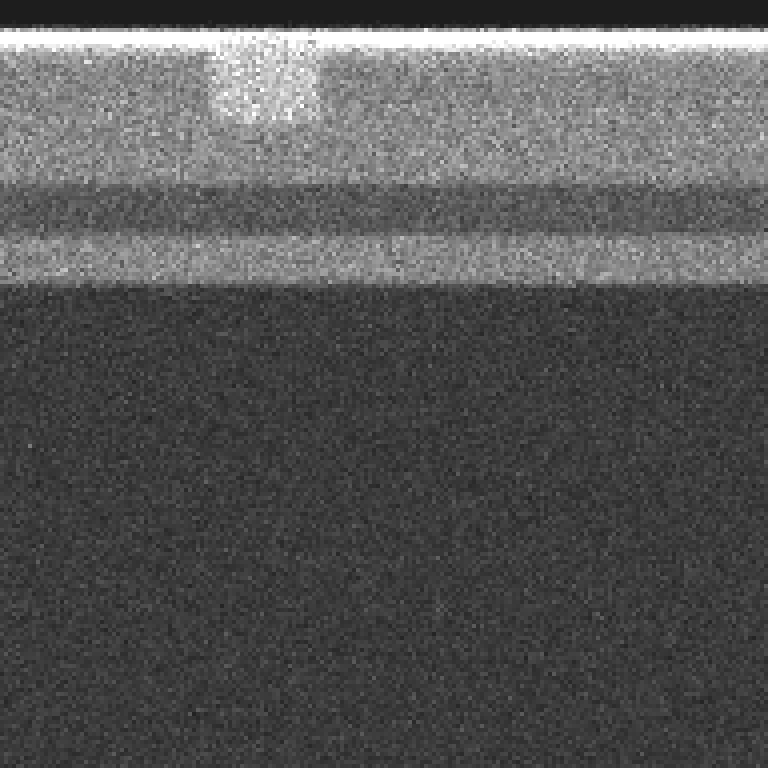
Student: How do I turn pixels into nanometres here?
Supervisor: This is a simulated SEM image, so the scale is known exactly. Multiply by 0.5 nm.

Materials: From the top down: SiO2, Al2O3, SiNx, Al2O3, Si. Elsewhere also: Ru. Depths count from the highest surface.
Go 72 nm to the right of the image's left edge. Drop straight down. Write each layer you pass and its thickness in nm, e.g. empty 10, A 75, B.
SiO2 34, Al2O3 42, SiNx 26, Al2O3 24, Si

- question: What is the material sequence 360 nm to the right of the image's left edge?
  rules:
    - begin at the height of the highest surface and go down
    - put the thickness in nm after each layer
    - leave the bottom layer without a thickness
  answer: SiO2 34, Al2O3 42, SiNx 26, Al2O3 24, Si